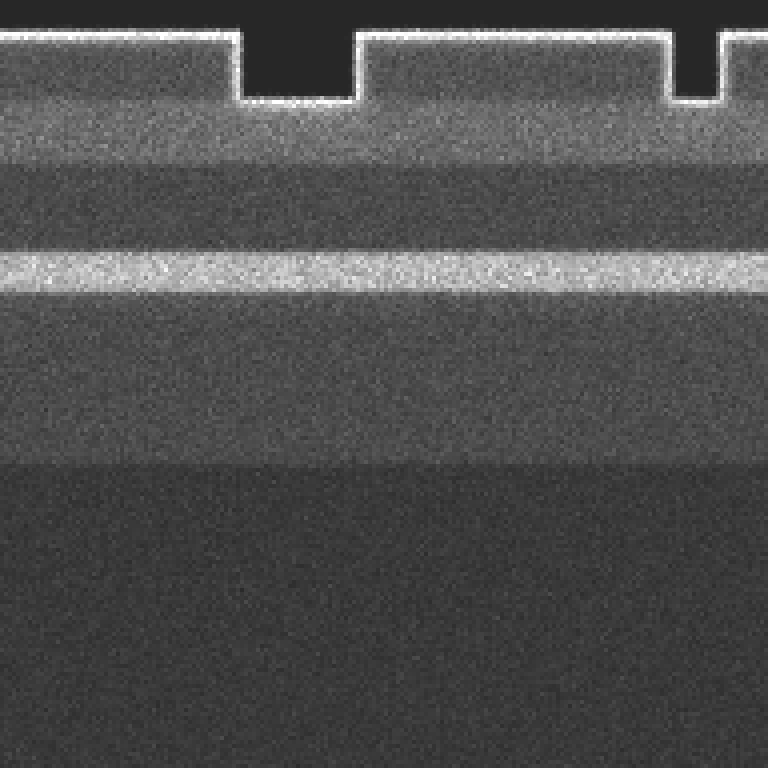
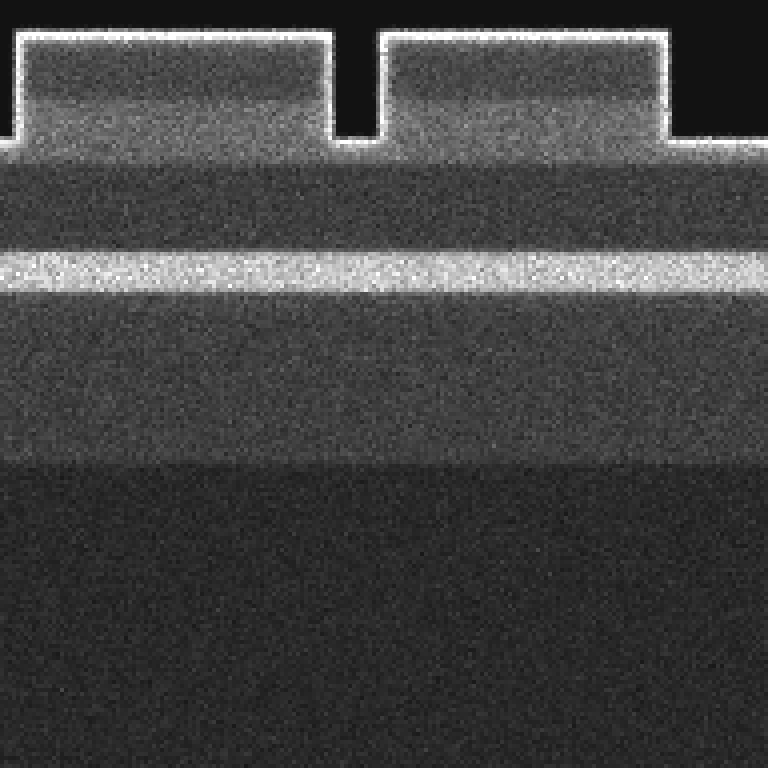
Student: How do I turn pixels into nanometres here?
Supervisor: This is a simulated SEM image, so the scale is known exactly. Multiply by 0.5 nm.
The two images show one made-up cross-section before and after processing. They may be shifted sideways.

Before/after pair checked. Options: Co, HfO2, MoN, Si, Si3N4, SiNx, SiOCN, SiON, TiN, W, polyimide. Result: removed Co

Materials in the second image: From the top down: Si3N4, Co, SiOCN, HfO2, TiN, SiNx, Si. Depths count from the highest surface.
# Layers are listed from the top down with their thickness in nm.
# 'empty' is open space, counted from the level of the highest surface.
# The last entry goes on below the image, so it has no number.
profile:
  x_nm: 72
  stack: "Si3N4 34, Co 32, SiOCN 44, HfO2 20, TiN 10, SiNx 76, Si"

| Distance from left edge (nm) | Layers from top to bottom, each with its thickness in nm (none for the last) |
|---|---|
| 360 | empty 54, Co 12, SiOCN 44, HfO2 20, TiN 10, SiNx 76, Si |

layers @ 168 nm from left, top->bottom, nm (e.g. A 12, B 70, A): empty 54, Co 12, SiOCN 44, HfO2 20, TiN 10, SiNx 76, Si